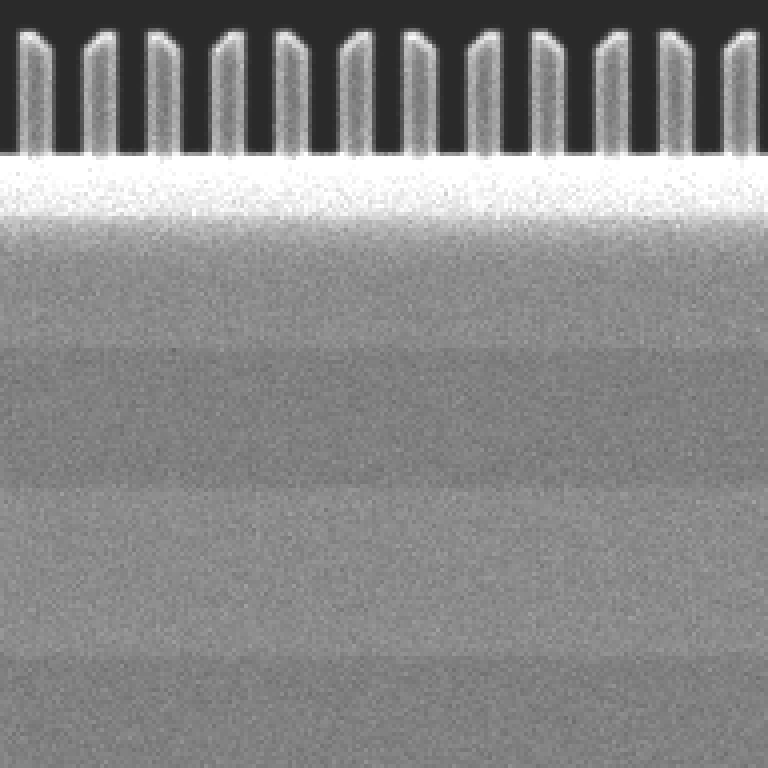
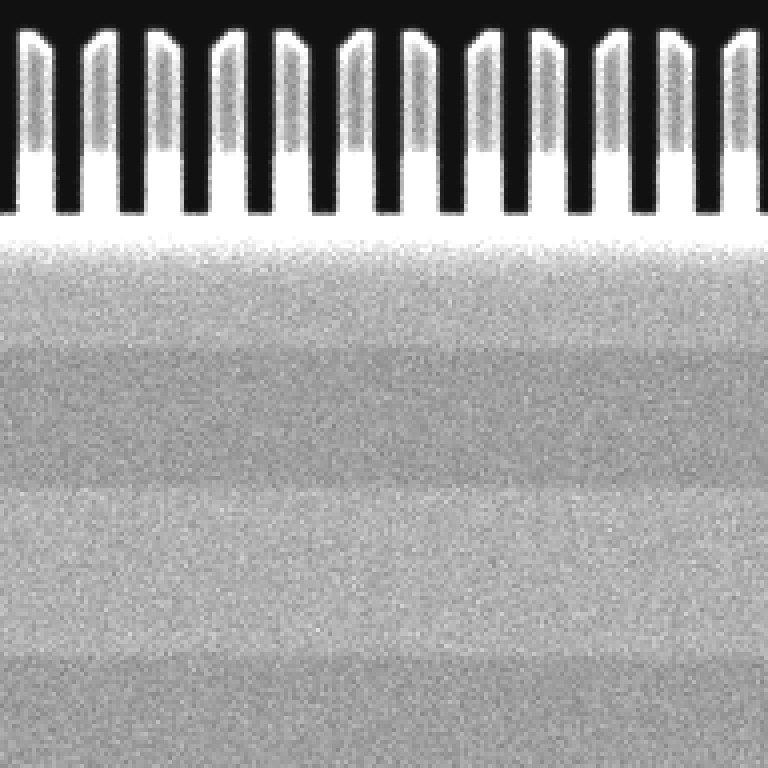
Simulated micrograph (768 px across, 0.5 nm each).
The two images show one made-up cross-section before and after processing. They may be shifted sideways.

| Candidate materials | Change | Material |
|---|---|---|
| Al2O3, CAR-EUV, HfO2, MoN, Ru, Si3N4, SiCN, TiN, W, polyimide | removed | HfO2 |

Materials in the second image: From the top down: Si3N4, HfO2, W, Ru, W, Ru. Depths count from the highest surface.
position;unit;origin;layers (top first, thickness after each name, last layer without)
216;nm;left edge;empty 8, Si3N4 54, HfO2 30, W 66, Ru 70, W 84, Ru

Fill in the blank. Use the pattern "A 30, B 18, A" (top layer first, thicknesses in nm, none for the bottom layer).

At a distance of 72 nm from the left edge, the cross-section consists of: empty 92, W 66, Ru 70, W 84, Ru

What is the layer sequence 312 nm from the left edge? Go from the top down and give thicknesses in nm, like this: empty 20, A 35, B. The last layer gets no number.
Si3N4 62, HfO2 30, W 66, Ru 70, W 84, Ru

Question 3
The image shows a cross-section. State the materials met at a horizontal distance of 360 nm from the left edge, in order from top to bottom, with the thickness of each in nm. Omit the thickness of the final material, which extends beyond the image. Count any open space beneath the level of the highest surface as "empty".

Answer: empty 92, W 66, Ru 70, W 84, Ru